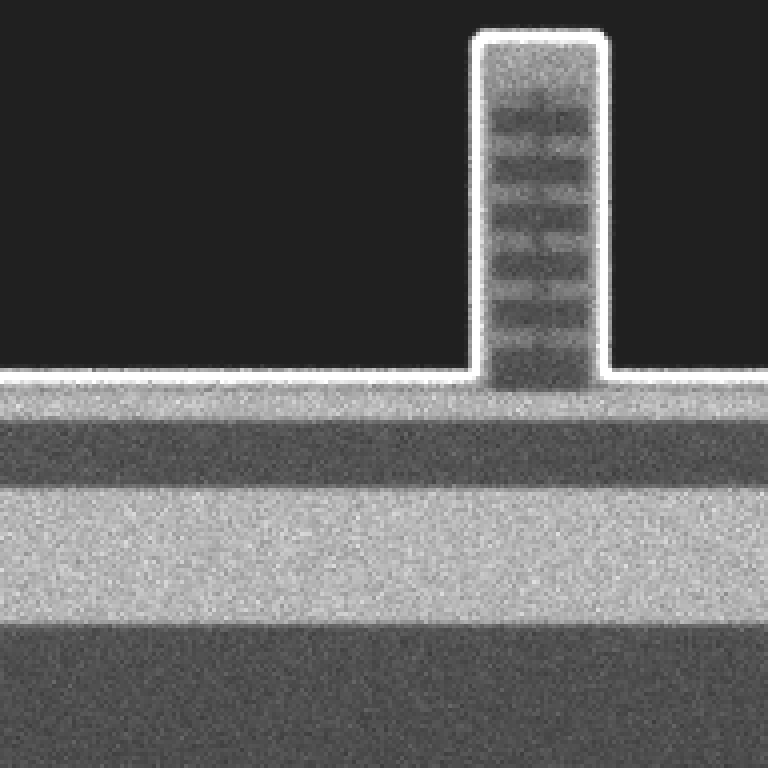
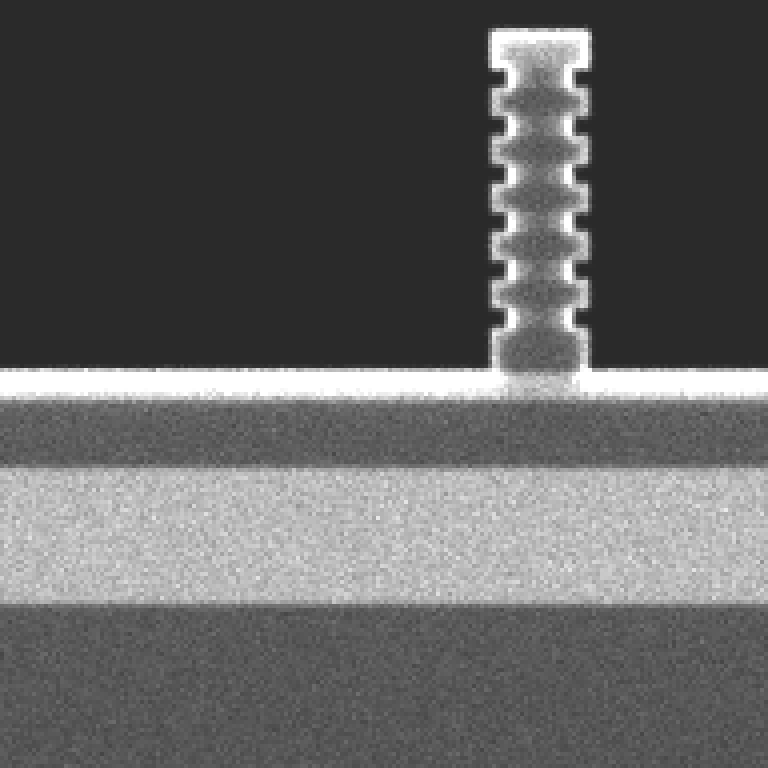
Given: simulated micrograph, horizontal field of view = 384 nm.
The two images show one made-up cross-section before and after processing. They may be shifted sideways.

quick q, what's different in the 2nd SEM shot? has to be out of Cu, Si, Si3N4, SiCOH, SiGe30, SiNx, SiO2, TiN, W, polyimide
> SiNx removed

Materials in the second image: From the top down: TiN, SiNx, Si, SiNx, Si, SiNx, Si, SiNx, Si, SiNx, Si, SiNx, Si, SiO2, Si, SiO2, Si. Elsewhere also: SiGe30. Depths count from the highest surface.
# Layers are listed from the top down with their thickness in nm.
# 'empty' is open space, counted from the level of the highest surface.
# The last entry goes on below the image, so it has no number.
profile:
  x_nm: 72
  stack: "empty 170, SiO2 14, Si 34, SiO2 68, Si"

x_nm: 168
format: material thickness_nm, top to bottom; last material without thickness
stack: empty 170, SiO2 14, Si 34, SiO2 68, Si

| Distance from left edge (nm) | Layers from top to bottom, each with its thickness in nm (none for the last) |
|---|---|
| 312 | empty 170, SiO2 14, Si 34, SiO2 68, Si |